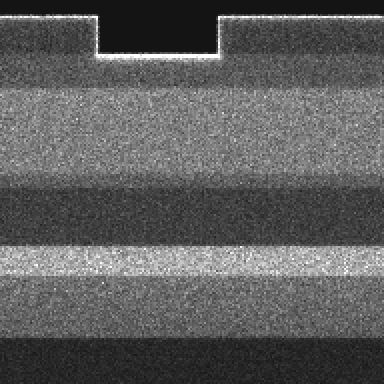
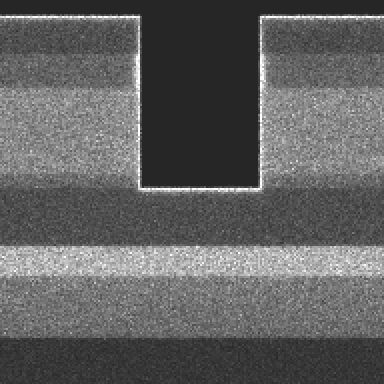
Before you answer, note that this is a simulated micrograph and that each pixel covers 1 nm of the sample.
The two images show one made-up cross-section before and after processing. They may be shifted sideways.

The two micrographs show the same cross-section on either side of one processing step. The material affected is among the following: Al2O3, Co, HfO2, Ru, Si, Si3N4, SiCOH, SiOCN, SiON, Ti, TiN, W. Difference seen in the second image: Al2O3 and Co and W removed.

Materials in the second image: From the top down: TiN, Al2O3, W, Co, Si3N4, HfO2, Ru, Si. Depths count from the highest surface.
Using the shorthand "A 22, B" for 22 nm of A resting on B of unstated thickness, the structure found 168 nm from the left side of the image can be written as empty 172, Si3N4 58, HfO2 30, Ru 62, Si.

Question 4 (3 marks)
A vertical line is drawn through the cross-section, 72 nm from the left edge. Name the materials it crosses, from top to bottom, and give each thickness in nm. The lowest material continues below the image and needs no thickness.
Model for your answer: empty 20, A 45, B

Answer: TiN 38, Al2O3 34, W 86, Co 14, Si3N4 58, HfO2 30, Ru 62, Si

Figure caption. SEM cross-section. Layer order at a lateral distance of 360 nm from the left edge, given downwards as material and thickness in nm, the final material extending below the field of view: TiN 38, Al2O3 34, W 86, Co 14, Si3N4 58, HfO2 30, Ru 62, Si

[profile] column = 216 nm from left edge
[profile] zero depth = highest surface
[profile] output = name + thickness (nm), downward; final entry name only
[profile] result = empty 172, Si3N4 58, HfO2 30, Ru 62, Si